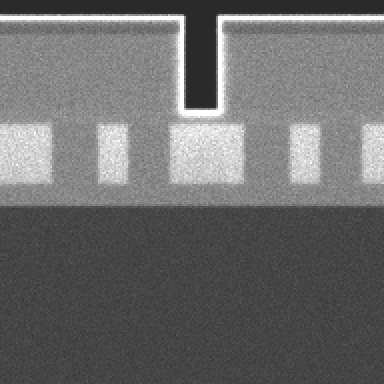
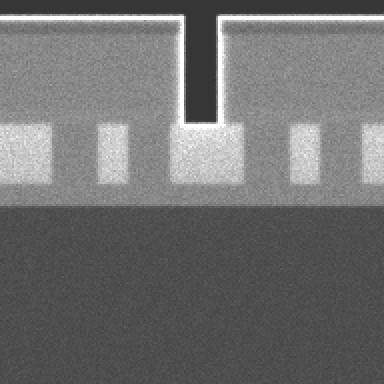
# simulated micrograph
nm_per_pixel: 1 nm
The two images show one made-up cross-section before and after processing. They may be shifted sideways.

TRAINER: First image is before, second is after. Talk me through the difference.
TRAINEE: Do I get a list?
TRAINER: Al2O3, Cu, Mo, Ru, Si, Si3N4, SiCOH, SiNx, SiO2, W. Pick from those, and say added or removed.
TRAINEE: removed: Al2O3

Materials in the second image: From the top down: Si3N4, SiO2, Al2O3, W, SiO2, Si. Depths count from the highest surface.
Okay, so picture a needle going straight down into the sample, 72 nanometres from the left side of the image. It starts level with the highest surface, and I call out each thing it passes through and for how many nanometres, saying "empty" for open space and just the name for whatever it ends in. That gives Si3N4 18, SiO2 76, Al2O3 14, SiO2 82, Si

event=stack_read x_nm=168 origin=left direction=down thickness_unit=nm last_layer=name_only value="Si3N4 18, SiO2 76, Al2O3 14, SiO2 82, Si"